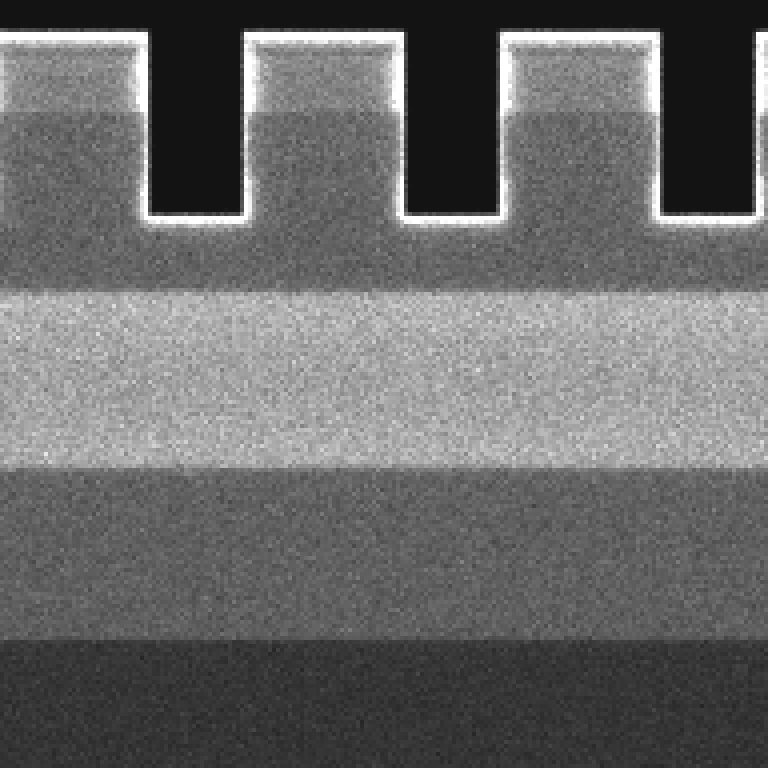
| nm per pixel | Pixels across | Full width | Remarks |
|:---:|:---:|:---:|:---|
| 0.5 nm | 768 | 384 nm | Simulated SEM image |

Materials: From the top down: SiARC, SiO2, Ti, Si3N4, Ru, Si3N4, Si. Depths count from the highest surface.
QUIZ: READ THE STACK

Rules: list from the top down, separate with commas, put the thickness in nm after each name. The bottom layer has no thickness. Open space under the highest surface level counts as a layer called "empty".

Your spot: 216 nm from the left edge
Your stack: empty 92, Si3N4 38, Ru 88, Si3N4 86, Si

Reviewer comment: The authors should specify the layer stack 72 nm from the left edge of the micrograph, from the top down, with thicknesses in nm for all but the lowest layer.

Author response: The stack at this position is SiARC 12, SiO2 28, Ti 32, Si3N4 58, Ru 88, Si3N4 86, Si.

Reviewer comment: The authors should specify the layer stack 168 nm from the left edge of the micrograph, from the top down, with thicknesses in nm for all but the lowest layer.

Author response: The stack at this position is SiARC 12, SiO2 28, Ti 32, Si3N4 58, Ru 88, Si3N4 86, Si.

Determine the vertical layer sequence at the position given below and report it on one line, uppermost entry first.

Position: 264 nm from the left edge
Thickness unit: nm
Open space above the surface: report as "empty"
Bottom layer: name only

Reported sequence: SiARC 12, SiO2 28, Ti 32, Si3N4 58, Ru 88, Si3N4 86, Si